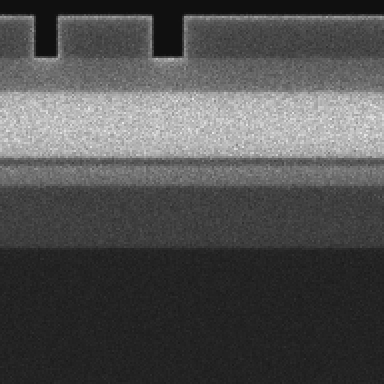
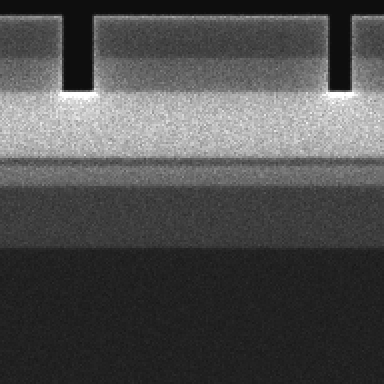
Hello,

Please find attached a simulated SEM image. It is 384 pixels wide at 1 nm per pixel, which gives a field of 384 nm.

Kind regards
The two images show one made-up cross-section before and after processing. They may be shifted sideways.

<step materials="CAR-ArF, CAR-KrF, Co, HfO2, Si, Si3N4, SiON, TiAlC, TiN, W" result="removed Co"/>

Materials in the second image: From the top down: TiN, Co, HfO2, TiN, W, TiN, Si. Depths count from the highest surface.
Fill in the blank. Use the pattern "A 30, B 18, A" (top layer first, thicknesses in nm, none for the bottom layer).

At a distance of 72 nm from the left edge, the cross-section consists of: empty 76, HfO2 66, TiN 8, W 20, TiN 62, Si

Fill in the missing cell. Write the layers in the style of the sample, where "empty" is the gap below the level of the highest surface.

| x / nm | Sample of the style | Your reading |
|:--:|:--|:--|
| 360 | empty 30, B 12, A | TiN 42, Co 34, HfO2 66, TiN 8, W 20, TiN 62, Si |